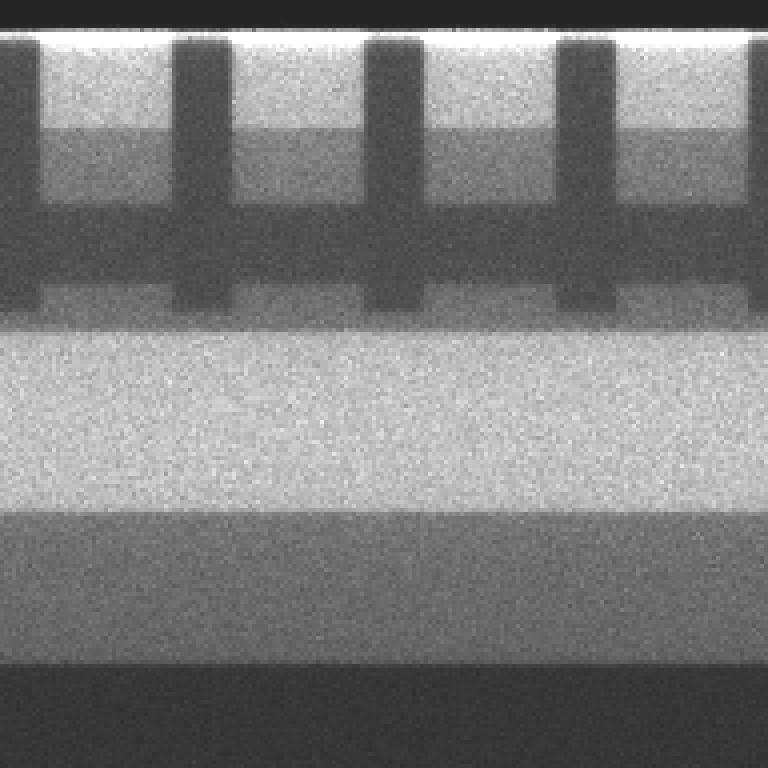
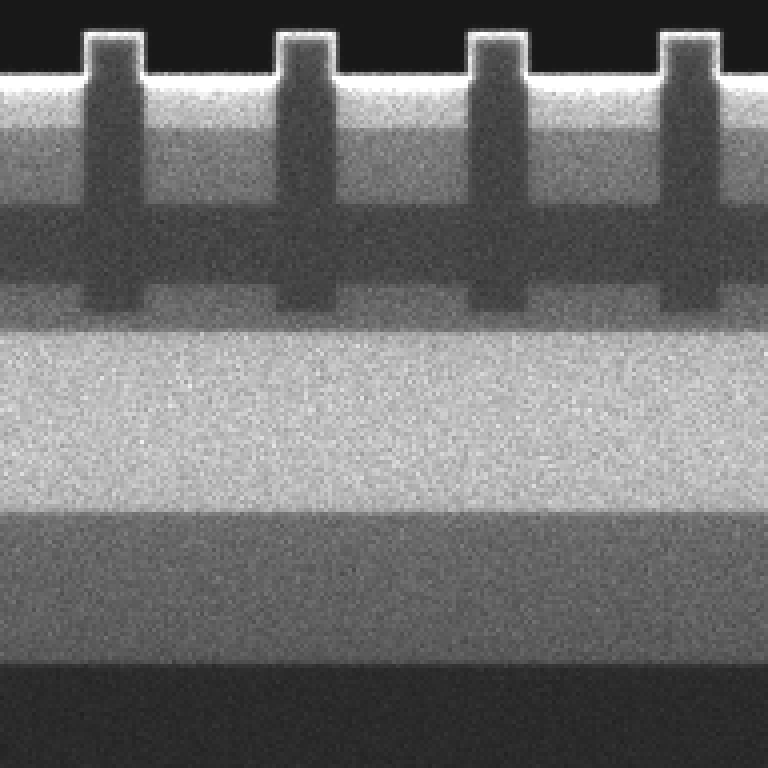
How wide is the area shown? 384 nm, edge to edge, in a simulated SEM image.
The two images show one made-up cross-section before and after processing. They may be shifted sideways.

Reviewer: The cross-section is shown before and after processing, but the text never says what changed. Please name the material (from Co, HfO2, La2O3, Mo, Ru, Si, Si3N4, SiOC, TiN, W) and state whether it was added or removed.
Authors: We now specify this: HfO2, removed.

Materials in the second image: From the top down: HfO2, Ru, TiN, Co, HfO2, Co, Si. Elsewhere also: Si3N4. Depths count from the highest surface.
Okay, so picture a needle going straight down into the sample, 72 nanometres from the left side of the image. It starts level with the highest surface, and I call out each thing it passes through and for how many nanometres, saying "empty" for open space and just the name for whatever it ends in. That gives empty 22, HfO2 26, Ru 38, TiN 40, Co 24, HfO2 90, Co 76, Si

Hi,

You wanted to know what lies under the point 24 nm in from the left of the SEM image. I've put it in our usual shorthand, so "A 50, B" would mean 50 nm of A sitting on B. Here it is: empty 22, HfO2 26, Ru 38, TiN 40, Co 24, HfO2 90, Co 76, Si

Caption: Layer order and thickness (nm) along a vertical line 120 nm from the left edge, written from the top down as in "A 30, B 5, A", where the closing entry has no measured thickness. empty 22, HfO2 26, Ru 38, TiN 40, Co 24, HfO2 90, Co 76, Si